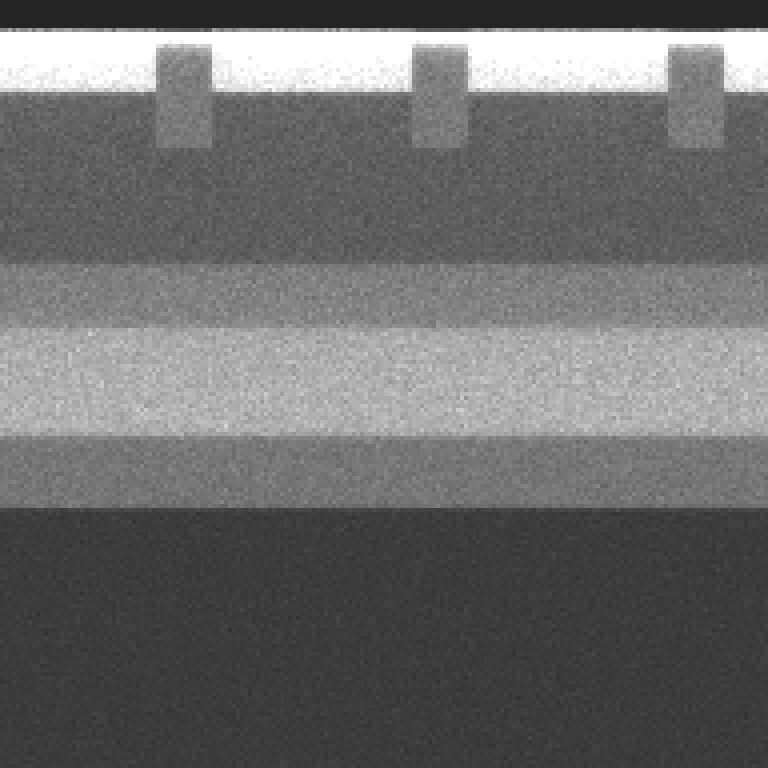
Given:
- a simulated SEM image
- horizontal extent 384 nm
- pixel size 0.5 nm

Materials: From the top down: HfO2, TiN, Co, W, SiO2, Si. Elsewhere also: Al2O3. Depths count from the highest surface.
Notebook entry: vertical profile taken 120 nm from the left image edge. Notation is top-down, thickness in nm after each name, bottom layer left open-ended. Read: HfO2 30, TiN 86, Co 32, W 54, SiO2 36, Si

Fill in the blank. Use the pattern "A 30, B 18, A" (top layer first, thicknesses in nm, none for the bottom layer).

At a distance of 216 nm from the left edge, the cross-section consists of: Al2O3 58, TiN 58, Co 32, W 54, SiO2 36, Si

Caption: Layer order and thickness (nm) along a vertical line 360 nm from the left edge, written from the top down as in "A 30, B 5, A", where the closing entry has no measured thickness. Al2O3 58, TiN 58, Co 32, W 54, SiO2 36, Si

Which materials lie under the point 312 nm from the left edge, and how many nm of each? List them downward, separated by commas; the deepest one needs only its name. HfO2 30, TiN 86, Co 32, W 54, SiO2 36, Si